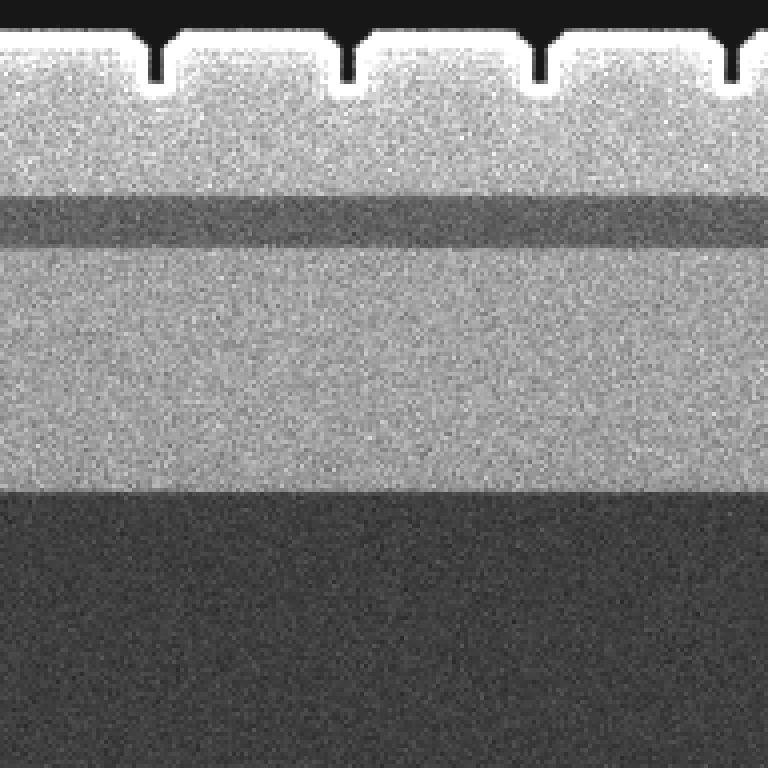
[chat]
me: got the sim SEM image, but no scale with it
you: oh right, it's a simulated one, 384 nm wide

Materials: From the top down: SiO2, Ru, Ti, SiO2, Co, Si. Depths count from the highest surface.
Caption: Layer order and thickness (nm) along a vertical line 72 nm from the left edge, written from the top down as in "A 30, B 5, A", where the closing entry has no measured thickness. empty 8, SiO2 30, Ru 44, Ti 26, SiO2 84, Co 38, Si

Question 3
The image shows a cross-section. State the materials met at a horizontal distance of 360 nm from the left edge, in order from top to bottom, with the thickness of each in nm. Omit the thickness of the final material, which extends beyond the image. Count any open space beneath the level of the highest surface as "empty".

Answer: empty 8, SiO2 30, Ru 44, Ti 26, SiO2 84, Co 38, Si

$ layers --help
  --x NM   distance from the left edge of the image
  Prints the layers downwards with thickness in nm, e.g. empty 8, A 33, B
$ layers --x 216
SiO2 12, Ru 70, Ti 26, SiO2 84, Co 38, Si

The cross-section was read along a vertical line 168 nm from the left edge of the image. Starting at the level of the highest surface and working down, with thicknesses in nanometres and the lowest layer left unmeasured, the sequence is empty 8, SiO2 30, Ru 44, Ti 26, SiO2 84, Co 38, Si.